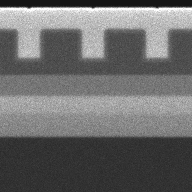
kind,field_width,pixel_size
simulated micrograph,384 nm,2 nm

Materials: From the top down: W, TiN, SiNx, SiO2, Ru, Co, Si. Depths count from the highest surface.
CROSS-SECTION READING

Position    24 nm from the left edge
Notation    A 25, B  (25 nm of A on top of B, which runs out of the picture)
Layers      W 42, TiN 8, SiNx 84, SiO2 42, Ru 36, Co 46, Si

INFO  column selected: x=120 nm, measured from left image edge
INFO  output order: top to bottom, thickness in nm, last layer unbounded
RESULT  W 42, TiN 8, SiNx 84, SiO2 42, Ru 36, Co 46, Si